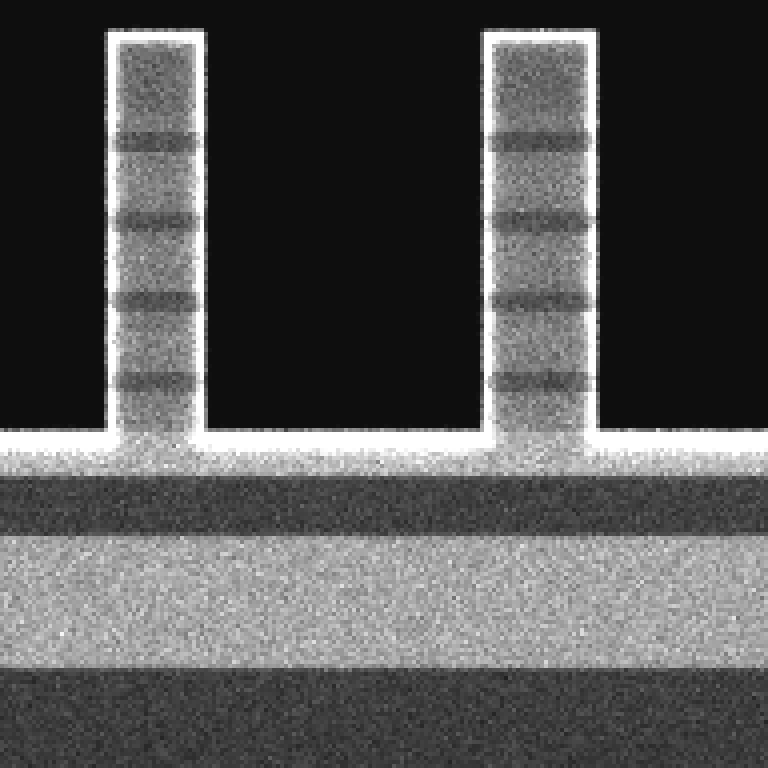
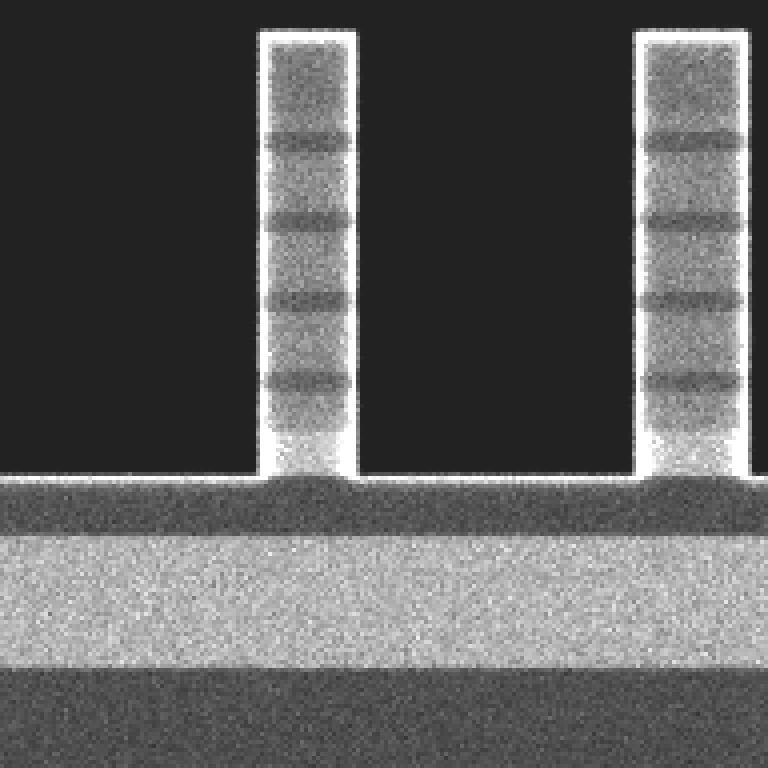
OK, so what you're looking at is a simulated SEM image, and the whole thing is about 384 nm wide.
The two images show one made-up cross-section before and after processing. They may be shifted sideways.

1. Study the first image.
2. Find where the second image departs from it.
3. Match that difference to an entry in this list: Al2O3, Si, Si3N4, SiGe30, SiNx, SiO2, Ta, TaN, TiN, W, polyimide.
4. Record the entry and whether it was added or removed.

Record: Al2O3 / removed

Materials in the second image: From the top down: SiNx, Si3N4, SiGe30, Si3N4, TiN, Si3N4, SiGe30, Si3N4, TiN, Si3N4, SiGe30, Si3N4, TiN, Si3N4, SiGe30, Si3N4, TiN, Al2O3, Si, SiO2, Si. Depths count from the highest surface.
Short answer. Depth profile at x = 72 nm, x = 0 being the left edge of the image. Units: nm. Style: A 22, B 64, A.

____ empty 222, Si 30, SiO2 66, Si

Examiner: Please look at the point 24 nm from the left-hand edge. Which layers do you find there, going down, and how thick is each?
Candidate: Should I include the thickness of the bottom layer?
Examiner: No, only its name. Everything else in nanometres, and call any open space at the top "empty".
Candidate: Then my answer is empty 222, Si 30, SiO2 66, Si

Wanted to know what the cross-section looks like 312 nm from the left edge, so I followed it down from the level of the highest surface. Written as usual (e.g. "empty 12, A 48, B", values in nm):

empty 222, Si 30, SiO2 66, Si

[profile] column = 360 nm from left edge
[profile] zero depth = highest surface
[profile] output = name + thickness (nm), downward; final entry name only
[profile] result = SiNx 40, Si3N4 10, SiGe30 10, Si3N4 10, TiN 10, Si3N4 10, SiGe30 10, Si3N4 10, TiN 10, Si3N4 10, SiGe30 10, Si3N4 10, TiN 10, Si3N4 10, SiGe30 10, Si3N4 10, TiN 10, Al2O3 22, Si 30, SiO2 66, Si